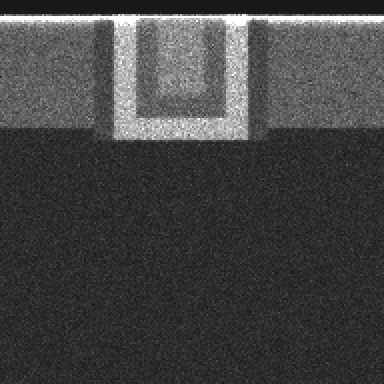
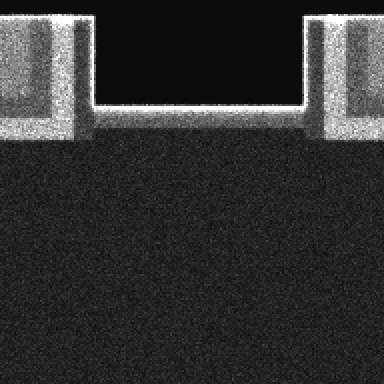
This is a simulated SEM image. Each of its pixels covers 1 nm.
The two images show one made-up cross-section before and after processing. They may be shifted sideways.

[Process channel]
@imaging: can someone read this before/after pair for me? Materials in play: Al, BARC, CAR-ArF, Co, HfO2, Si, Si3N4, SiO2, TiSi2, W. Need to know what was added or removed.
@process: SiO2 removed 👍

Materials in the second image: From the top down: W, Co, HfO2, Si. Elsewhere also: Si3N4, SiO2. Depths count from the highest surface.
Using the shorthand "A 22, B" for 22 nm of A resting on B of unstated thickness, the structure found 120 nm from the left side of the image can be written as empty 90, SiO2 22, Si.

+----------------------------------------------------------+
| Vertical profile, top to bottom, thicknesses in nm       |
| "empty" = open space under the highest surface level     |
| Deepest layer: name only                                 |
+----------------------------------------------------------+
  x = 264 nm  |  empty 90, SiO2 22, Si